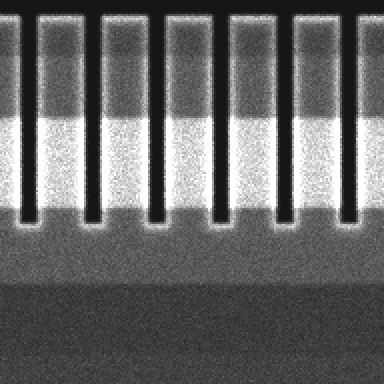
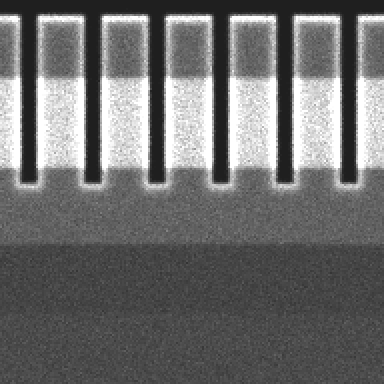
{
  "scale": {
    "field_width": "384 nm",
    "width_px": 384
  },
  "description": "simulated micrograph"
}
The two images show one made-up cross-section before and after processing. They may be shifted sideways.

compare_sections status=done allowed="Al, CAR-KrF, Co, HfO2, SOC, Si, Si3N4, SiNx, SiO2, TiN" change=removed material="SOC"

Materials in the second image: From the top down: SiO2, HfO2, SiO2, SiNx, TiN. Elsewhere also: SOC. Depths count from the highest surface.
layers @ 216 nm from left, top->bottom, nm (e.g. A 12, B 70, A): empty 168, SiO2 60, SiNx 70, TiN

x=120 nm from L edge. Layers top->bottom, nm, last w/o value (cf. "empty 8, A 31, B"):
SiO2 62, HfO2 90, SiO2 76, SiNx 70, TiN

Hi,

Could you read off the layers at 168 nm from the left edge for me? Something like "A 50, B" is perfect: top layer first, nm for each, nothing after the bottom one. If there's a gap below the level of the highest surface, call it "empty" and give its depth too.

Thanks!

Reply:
SiO2 62, HfO2 90, SiO2 76, SiNx 70, TiN